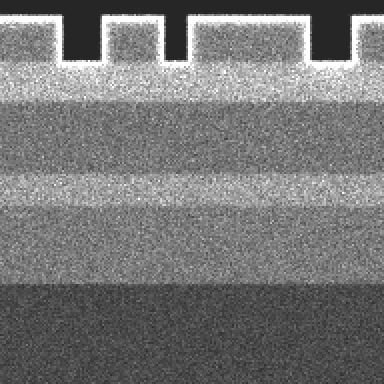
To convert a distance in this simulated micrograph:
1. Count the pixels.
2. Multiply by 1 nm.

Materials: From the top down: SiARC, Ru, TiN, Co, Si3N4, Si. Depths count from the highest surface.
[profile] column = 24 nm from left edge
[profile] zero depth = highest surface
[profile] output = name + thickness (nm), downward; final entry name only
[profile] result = SiARC 46, Ru 40, TiN 72, Co 32, Si3N4 78, Si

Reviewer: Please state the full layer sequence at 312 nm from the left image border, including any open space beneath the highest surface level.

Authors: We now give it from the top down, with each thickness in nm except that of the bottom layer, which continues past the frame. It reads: empty 46, Ru 40, TiN 72, Co 32, Si3N4 78, Si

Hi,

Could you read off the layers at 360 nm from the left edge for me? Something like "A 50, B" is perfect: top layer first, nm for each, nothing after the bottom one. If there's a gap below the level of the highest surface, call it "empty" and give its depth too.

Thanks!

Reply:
SiARC 46, Ru 40, TiN 72, Co 32, Si3N4 78, Si